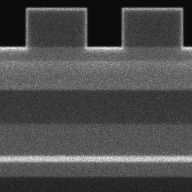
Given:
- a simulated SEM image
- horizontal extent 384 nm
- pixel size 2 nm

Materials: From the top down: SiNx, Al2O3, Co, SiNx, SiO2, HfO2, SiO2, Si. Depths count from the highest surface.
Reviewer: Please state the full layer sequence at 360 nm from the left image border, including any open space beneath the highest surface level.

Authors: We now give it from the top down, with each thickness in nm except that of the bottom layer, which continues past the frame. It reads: SiNx 78, Al2O3 28, Co 58, SiNx 68, SiO2 64, HfO2 12, SiO2 30, Si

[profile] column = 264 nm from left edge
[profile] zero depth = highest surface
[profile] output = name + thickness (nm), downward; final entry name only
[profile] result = SiNx 78, Al2O3 28, Co 58, SiNx 68, SiO2 64, HfO2 12, SiO2 30, Si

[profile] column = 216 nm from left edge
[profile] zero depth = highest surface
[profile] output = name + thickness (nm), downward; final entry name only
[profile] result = empty 78, Al2O3 28, Co 58, SiNx 68, SiO2 64, HfO2 12, SiO2 30, Si